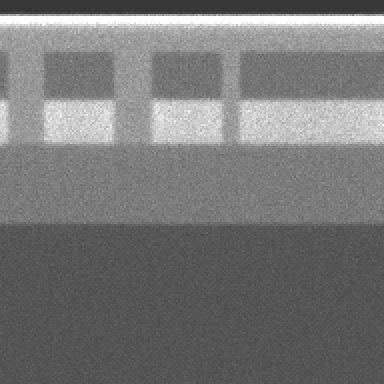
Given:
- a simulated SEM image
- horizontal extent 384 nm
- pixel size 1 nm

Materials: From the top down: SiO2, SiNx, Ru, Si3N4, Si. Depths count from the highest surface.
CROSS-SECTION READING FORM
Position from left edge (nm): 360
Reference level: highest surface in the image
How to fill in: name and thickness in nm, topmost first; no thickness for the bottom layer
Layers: SiO2 36, SiNx 48, Ru 44, Si3N4 80, Si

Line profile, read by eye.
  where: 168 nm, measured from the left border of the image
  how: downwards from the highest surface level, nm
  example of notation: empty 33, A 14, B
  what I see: SiO2 36, SiNx 48, Ru 44, Si3N4 80, Si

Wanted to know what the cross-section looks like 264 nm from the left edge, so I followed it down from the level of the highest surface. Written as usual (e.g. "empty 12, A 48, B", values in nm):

SiO2 36, SiNx 48, Ru 44, Si3N4 80, Si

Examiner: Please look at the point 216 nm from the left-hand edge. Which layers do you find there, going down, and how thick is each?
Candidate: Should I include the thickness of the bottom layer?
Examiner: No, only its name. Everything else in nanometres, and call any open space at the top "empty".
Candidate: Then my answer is SiO2 36, SiNx 48, Ru 44, Si3N4 80, Si